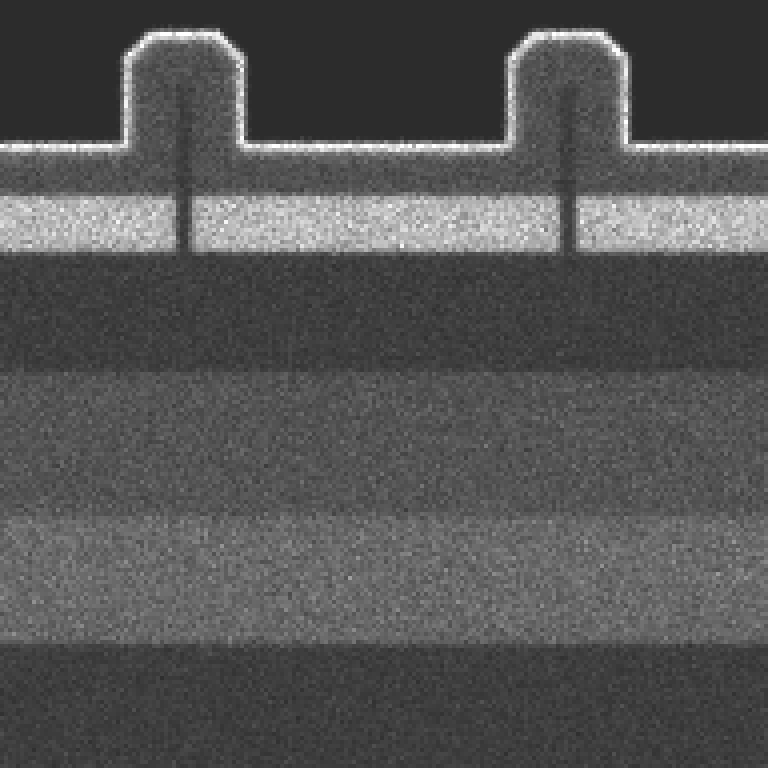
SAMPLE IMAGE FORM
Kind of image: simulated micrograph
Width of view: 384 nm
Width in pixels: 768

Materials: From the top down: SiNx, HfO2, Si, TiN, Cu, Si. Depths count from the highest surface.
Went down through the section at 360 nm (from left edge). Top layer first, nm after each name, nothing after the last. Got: empty 56, SiNx 26, HfO2 28, Si 60, TiN 72, Cu 64, Si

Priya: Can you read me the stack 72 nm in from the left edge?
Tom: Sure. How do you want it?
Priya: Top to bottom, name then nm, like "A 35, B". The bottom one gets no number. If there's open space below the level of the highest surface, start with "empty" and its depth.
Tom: empty 2, SiNx 80, HfO2 28, Si 60, TiN 72, Cu 64, Si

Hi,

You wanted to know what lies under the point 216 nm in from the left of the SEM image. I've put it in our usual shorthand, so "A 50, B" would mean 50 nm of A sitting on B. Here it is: empty 56, SiNx 26, HfO2 28, Si 60, TiN 72, Cu 64, Si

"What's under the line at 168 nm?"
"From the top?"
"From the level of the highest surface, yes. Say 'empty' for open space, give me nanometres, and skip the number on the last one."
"empty 56, SiNx 26, HfO2 28, Si 60, TiN 72, Cu 64, Si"